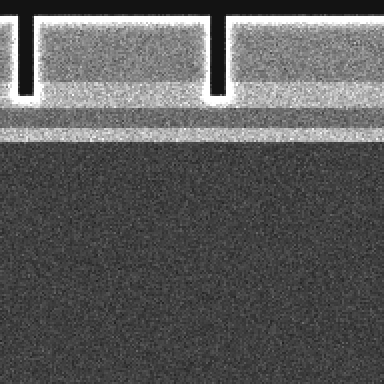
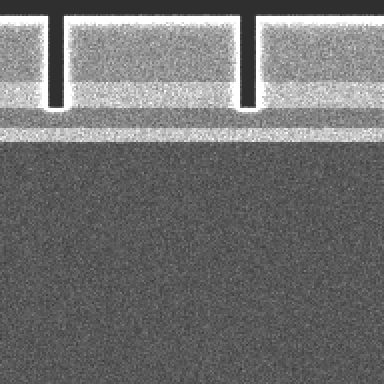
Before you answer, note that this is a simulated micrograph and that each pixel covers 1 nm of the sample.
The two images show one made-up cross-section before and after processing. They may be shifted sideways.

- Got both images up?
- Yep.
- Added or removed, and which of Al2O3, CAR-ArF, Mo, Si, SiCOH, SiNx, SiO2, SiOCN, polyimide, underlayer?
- removed, SiO2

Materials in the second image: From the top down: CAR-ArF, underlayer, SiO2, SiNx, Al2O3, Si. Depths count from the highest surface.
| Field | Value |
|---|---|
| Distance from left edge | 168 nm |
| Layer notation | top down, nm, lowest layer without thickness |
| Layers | CAR-ArF 40, underlayer 26, SiO2 26, SiNx 20, Al2O3 14, Si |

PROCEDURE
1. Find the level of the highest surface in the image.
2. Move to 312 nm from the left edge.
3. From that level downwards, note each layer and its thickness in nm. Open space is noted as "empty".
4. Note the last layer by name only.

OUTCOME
CAR-ArF 40, underlayer 26, SiO2 26, SiNx 20, Al2O3 14, Si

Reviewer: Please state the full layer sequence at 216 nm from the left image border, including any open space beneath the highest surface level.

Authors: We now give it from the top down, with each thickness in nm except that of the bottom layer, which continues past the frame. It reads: CAR-ArF 40, underlayer 26, SiO2 26, SiNx 20, Al2O3 14, Si